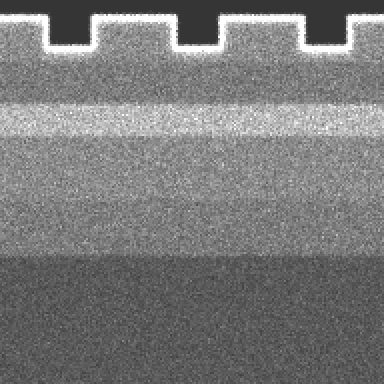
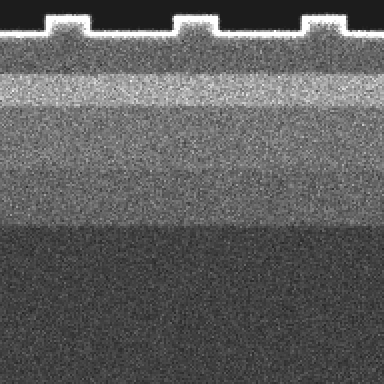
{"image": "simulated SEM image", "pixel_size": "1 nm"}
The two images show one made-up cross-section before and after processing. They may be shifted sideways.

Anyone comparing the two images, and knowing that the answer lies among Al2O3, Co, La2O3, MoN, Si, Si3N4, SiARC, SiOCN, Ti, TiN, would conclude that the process removed Si3N4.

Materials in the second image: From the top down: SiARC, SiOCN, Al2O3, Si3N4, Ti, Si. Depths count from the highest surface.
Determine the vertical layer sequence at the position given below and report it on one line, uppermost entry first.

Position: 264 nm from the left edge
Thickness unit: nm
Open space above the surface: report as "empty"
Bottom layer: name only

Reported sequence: empty 16, SiOCN 42, Al2O3 32, Si3N4 64, Ti 56, Si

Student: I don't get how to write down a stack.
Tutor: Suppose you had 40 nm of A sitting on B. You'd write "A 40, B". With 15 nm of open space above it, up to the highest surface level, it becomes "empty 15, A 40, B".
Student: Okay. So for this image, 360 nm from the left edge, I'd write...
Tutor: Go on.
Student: empty 16, SiOCN 42, Al2O3 32, Si3N4 64, Ti 56, Si